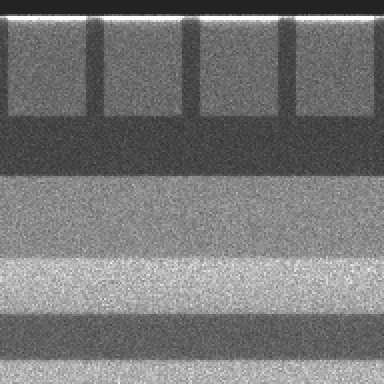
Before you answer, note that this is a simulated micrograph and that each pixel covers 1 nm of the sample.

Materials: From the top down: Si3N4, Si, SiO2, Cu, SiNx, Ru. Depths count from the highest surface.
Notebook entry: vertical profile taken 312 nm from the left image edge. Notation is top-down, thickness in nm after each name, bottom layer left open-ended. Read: Si3N4 100, Si 60, SiO2 82, Cu 56, SiNx 46, Ru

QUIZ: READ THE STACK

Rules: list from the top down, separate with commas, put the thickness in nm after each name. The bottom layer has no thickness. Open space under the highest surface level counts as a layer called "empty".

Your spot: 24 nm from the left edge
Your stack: Si3N4 100, Si 60, SiO2 82, Cu 56, SiNx 46, Ru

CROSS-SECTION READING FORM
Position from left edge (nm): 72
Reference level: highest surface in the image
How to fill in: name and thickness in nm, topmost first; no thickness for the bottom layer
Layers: Si3N4 100, Si 60, SiO2 82, Cu 56, SiNx 46, Ru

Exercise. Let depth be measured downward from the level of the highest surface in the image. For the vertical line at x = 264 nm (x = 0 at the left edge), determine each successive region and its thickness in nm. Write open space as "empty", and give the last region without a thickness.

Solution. Si3N4 100, Si 60, SiO2 82, Cu 56, SiNx 46, Ru